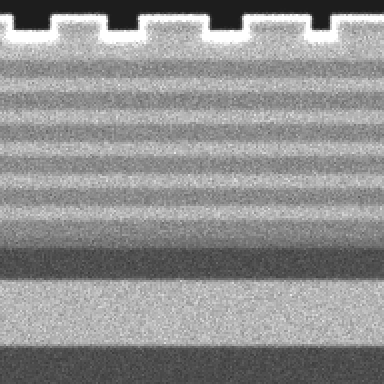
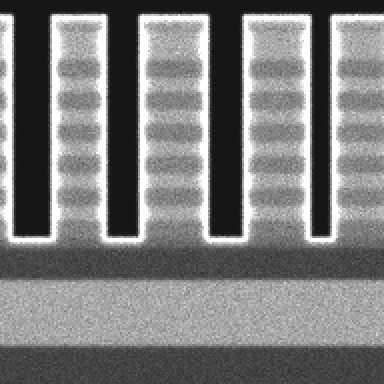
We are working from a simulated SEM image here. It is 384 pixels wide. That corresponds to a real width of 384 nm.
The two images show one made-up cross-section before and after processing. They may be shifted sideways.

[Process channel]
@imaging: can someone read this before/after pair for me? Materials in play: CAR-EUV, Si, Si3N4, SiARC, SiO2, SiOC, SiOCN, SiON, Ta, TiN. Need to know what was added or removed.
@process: Si3N4 and SiO2 removed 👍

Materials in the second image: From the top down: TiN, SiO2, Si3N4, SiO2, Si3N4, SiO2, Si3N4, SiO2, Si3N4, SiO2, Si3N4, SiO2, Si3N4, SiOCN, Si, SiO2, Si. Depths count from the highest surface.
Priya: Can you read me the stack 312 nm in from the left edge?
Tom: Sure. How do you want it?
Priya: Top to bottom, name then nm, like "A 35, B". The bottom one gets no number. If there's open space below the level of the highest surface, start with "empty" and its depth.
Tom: empty 222, SiOCN 10, Si 32, SiO2 66, Si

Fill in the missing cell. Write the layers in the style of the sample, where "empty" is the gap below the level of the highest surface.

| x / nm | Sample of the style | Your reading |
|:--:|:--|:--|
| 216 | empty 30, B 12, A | empty 222, SiOCN 10, Si 32, SiO2 66, Si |